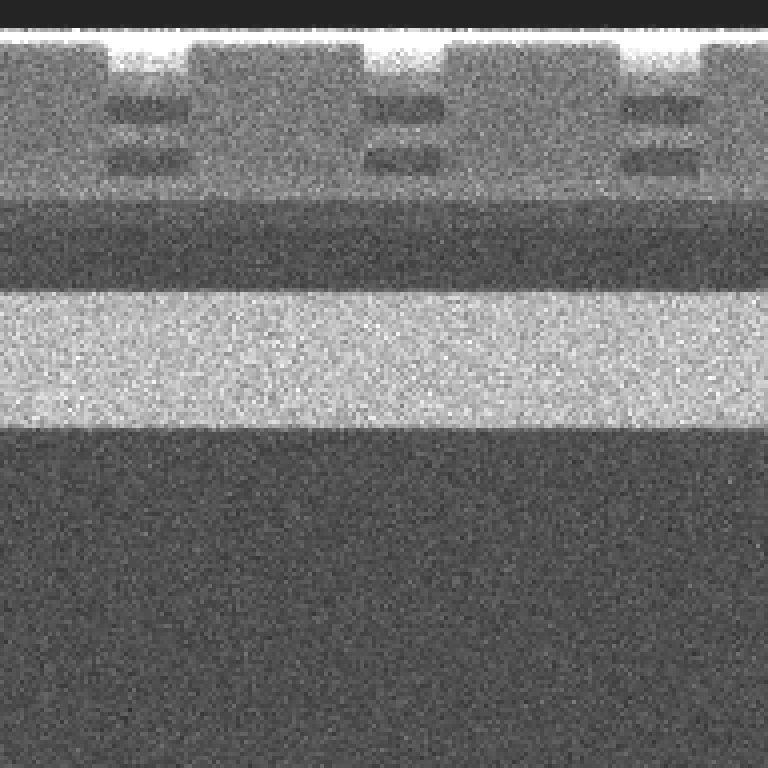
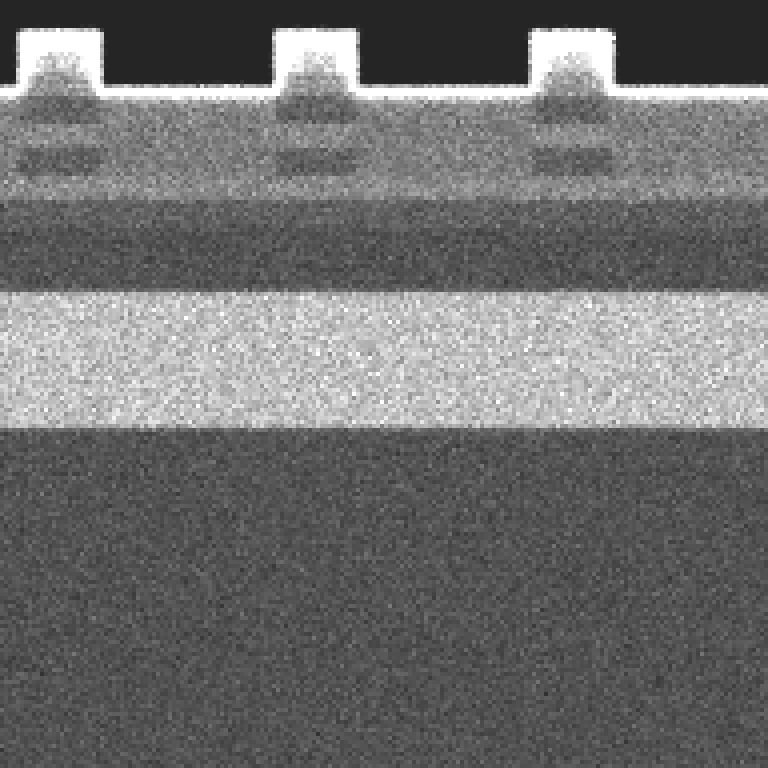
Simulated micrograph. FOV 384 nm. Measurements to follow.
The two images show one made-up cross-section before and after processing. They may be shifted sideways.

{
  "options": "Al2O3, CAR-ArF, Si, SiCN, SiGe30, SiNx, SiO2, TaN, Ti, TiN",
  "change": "removed",
  "material": "SiNx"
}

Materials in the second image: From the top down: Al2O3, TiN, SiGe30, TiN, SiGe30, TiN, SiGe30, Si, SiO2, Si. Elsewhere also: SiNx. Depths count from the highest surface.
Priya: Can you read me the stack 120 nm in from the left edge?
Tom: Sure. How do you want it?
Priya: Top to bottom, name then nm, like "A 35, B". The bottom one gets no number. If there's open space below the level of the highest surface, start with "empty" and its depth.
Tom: empty 28, SiNx 44, TiN 12, SiGe30 14, Si 32, SiO2 68, Si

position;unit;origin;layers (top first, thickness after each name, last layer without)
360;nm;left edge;empty 28, SiNx 44, TiN 12, SiGe30 14, Si 32, SiO2 68, Si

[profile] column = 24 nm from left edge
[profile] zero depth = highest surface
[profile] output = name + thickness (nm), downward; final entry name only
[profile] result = Al2O3 20, TiN 12, SiGe30 14, TiN 12, SiGe30 14, TiN 12, SiGe30 14, Si 32, SiO2 68, Si